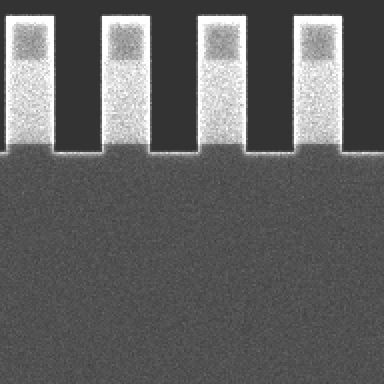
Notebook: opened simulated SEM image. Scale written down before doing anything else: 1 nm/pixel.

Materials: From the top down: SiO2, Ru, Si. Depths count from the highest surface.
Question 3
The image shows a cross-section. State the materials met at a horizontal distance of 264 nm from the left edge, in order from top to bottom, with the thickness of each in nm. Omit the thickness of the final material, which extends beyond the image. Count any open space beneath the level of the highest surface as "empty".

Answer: empty 136, Si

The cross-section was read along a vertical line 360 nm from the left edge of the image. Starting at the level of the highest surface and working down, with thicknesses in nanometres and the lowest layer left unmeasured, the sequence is empty 136, Si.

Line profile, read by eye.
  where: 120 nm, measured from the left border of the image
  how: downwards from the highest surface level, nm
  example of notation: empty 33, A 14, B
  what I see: SiO2 44, Ru 84, Si